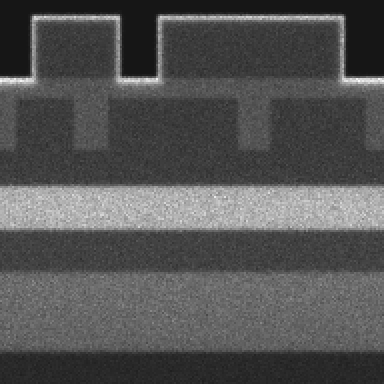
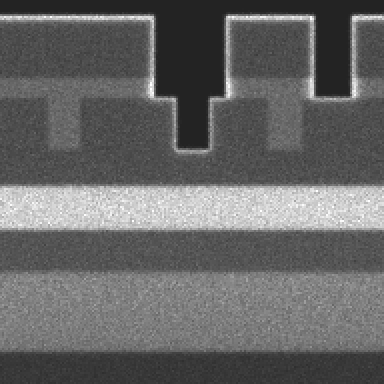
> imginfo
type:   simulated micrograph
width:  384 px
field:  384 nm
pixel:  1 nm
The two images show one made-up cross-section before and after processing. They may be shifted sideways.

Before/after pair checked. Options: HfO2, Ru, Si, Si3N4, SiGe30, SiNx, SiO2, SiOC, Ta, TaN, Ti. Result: removed SiO2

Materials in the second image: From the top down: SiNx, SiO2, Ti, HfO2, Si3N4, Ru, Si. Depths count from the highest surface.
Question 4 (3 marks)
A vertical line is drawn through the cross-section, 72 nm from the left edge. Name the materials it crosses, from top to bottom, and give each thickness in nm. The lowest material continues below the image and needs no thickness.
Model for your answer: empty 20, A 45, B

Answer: SiNx 62, SiO2 72, Ti 36, HfO2 44, Si3N4 42, Ru 80, Si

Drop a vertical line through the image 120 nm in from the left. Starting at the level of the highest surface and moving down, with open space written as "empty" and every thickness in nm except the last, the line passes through SiNx 62, SiO2 20, Ti 88, HfO2 44, Si3N4 42, Ru 80, Si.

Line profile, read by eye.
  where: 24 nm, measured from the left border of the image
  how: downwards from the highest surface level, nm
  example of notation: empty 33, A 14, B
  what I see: SiNx 62, SiO2 20, Ti 88, HfO2 44, Si3N4 42, Ru 80, Si